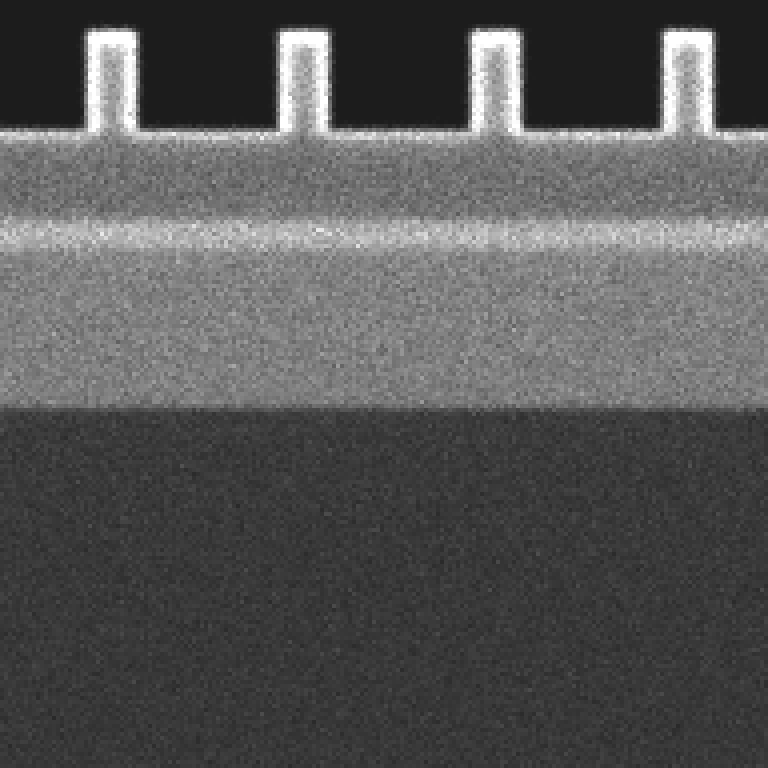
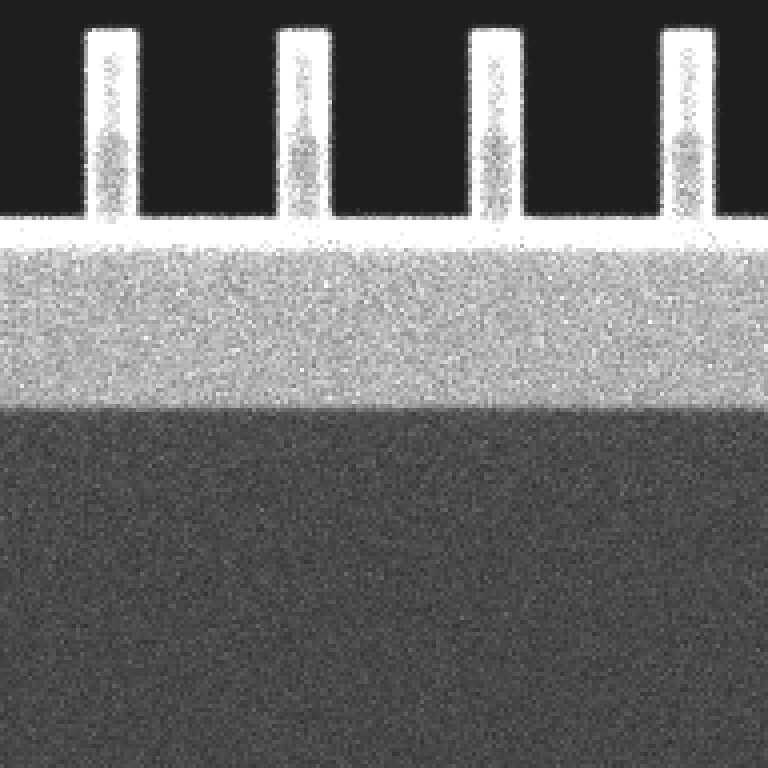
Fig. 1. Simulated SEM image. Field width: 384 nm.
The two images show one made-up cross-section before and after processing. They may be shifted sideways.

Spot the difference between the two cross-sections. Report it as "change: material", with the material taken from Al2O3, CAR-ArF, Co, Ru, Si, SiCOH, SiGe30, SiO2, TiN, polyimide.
removed: TiN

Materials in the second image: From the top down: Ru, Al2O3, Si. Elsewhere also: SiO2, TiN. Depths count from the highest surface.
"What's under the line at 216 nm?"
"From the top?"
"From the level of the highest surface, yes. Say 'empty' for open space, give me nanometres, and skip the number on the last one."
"empty 94, Ru 14, Al2O3 80, Si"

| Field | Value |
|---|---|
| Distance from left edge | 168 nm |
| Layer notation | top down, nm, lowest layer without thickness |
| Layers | empty 94, Ru 14, Al2O3 80, Si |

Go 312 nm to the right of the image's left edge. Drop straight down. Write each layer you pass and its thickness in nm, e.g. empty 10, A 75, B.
empty 94, Ru 14, Al2O3 80, Si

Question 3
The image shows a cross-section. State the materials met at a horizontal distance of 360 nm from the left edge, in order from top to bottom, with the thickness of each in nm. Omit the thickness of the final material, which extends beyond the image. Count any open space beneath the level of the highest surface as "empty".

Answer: empty 94, Ru 14, Al2O3 80, Si